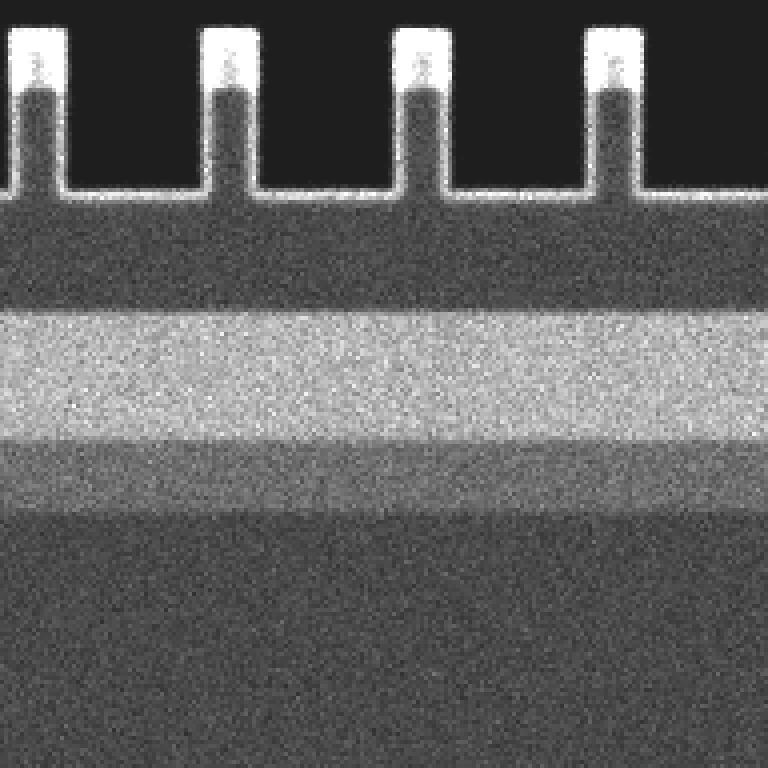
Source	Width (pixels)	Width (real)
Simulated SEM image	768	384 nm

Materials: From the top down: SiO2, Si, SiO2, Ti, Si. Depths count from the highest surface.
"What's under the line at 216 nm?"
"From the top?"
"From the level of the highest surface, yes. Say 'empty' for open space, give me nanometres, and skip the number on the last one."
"SiO2 28, Si 112, SiO2 64, Ti 36, Si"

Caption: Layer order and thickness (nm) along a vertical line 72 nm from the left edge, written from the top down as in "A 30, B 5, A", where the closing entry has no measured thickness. empty 80, Si 60, SiO2 64, Ti 36, Si